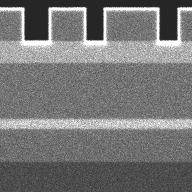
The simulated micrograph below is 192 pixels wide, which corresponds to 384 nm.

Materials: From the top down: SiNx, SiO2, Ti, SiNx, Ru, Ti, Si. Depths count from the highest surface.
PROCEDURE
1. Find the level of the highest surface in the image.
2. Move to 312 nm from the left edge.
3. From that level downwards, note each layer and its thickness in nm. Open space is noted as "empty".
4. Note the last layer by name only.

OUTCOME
SiNx 66, SiO2 44, Ti 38, SiNx 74, Ru 20, Ti 66, Si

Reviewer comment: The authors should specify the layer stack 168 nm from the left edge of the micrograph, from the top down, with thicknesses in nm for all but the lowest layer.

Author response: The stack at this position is SiNx 66, SiO2 44, Ti 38, SiNx 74, Ru 20, Ti 66, Si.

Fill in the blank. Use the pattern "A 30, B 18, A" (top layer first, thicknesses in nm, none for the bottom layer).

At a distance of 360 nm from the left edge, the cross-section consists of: SiNx 66, SiO2 44, Ti 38, SiNx 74, Ru 20, Ti 66, Si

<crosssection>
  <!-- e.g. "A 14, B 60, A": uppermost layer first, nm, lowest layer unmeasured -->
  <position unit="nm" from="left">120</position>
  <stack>SiNx 66, SiO2 44, Ti 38, SiNx 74, Ru 20, Ti 66, Si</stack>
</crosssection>